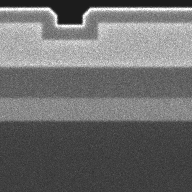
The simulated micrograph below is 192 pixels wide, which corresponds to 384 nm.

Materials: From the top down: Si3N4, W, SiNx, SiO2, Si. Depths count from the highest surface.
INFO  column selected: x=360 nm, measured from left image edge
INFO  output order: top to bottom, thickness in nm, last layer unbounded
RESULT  Si3N4 30, W 88, SiNx 62, SiO2 46, Si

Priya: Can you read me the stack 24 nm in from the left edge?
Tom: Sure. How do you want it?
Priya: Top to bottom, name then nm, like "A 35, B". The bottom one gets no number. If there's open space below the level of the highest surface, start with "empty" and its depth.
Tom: Si3N4 30, W 88, SiNx 62, SiO2 46, Si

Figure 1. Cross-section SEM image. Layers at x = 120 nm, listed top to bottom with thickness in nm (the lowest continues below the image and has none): empty 34, Si3N4 30, W 54, SiNx 62, SiO2 46, Si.